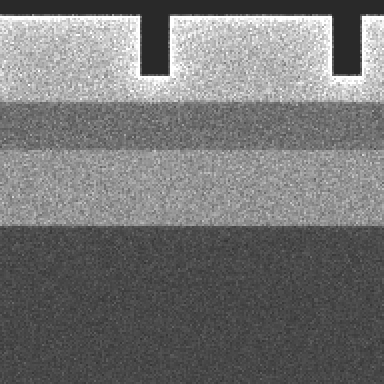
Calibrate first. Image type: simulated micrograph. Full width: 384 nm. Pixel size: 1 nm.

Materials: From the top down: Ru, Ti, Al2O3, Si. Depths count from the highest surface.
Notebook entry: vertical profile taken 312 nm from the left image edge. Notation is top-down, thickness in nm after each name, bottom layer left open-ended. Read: Ru 86, Ti 48, Al2O3 76, Si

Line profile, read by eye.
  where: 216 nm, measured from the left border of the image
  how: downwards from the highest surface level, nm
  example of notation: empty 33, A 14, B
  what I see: Ru 86, Ti 48, Al2O3 76, Si